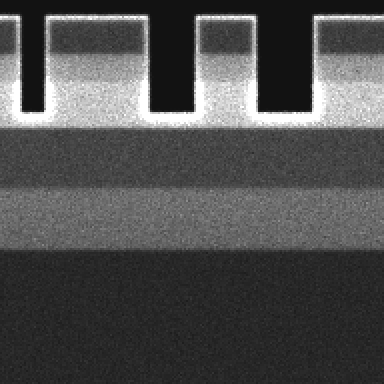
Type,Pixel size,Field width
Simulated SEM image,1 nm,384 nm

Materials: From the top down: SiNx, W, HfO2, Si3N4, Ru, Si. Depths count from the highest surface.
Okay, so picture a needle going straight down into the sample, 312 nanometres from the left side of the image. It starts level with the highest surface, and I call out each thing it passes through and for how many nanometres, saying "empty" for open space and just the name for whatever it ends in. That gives empty 98, HfO2 14, Si3N4 60, Ru 62, Si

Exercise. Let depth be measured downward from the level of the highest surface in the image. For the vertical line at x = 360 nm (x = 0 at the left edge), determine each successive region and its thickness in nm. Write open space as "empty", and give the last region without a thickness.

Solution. SiNx 38, W 28, HfO2 46, Si3N4 60, Ru 62, Si